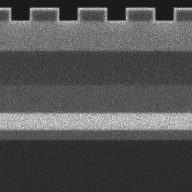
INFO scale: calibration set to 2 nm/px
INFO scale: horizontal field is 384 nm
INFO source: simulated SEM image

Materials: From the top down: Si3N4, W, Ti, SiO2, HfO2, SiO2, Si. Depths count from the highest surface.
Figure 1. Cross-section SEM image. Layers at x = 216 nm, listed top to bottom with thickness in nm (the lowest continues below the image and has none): empty 26, W 60, Ti 68, SiO2 56, HfO2 34, SiO2 20, Si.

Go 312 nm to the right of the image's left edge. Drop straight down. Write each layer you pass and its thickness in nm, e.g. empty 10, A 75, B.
empty 26, W 60, Ti 68, SiO2 56, HfO2 34, SiO2 20, Si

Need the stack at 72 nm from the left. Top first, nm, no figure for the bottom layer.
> Si3N4 26, W 60, Ti 68, SiO2 56, HfO2 34, SiO2 20, Si